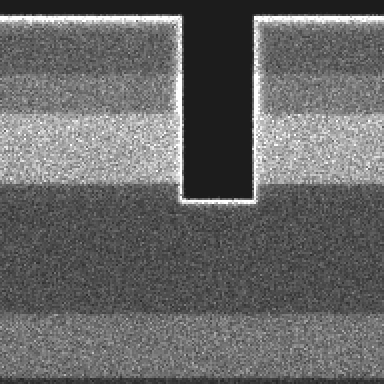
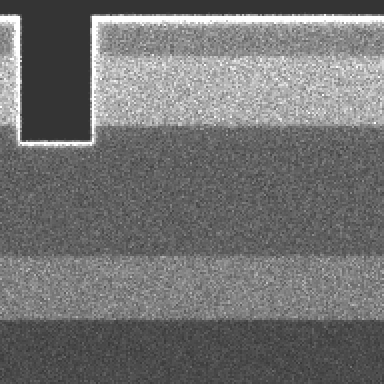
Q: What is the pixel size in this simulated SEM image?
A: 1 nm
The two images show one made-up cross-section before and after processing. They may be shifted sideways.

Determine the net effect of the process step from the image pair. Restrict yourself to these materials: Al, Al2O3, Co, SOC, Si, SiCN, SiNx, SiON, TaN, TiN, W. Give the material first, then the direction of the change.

SOC: removed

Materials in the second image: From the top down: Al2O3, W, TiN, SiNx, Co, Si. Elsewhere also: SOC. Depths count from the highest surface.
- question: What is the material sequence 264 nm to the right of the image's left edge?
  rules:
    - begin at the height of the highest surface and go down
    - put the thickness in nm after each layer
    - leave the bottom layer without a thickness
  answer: Al2O3 40, W 70, TiN 16, SiNx 114, Co 64, Si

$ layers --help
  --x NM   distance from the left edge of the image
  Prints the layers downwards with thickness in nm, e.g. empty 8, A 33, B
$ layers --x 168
Al2O3 40, W 70, TiN 16, SiNx 114, Co 64, Si